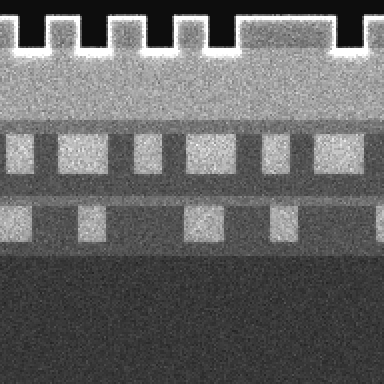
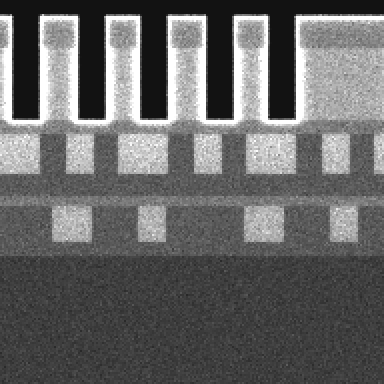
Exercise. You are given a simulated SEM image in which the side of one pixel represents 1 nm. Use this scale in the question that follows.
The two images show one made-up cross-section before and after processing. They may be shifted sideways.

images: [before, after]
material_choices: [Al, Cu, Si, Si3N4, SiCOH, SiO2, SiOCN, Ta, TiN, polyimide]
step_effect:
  removed: SiO2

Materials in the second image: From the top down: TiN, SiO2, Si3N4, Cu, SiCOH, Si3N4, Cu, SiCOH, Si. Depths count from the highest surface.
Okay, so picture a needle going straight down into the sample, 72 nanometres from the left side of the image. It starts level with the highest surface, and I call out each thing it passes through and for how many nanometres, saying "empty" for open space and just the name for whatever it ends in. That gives TiN 32, SiO2 72, Si3N4 14, Cu 40, SiCOH 22, Si3N4 10, Cu 36, SiCOH 14, Si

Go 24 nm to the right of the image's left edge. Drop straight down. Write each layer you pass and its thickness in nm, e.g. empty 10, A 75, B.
empty 104, Si3N4 14, Cu 40, SiCOH 22, Si3N4 10, SiCOH 50, Si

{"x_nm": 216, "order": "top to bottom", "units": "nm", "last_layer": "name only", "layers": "empty 104, Si3N4 14, Cu 40, SiCOH 22, Si3N4 10, SiCOH 50, Si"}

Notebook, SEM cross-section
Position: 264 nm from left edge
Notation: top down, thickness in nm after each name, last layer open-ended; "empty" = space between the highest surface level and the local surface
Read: TiN 32, SiO2 72, Si3N4 14, Cu 40, SiCOH 22, Si3N4 10, Cu 36, SiCOH 14, Si